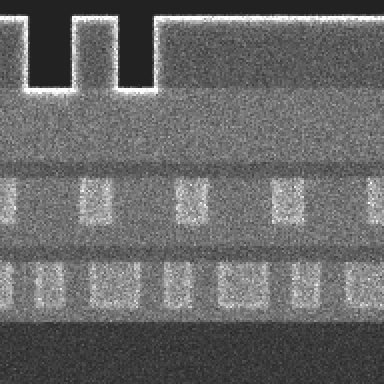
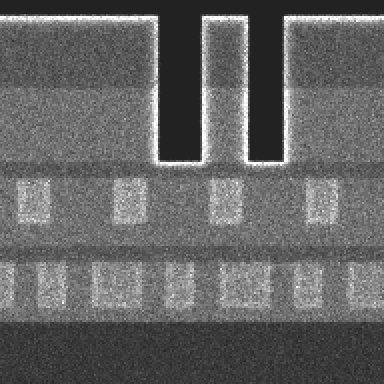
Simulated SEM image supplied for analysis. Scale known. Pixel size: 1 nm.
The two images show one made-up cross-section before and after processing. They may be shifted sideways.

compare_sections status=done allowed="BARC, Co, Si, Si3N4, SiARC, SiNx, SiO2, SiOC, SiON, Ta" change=removed material="SiO2"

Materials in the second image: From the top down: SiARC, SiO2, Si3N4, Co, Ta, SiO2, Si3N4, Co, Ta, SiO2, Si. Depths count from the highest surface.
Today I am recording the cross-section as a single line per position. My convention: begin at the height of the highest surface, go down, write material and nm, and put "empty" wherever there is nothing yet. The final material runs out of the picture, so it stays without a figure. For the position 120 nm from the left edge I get SiARC 72, SiO2 74, Si3N4 16, Co 40, Ta 6, SiO2 22, Si3N4 16, Co 40, Ta 6, SiO2 14, Si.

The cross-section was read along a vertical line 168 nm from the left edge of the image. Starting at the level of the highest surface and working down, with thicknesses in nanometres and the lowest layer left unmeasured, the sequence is empty 146, Si3N4 16, SiO2 68, Si3N4 16, Ta 46, SiO2 14, Si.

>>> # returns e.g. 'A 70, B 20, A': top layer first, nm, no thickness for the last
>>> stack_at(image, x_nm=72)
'SiARC 72, SiO2 74, Si3N4 16, SiO2 68, Si3N4 16, SiO2 60, Si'